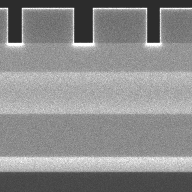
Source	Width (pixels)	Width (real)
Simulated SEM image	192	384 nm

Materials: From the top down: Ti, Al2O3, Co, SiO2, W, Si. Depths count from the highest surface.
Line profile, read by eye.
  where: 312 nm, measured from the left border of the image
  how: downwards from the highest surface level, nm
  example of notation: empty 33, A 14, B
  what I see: empty 70, Al2O3 58, Co 84, SiO2 86, W 30, Si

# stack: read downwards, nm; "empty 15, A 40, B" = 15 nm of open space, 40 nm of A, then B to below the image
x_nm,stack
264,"Ti 70, Al2O3 58, Co 84, SiO2 86, W 30, Si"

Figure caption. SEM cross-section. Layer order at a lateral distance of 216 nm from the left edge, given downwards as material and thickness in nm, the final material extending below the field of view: Ti 70, Al2O3 58, Co 84, SiO2 86, W 30, Si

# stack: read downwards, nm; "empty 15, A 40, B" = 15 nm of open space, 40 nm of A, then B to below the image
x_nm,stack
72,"Ti 70, Al2O3 58, Co 84, SiO2 86, W 30, Si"